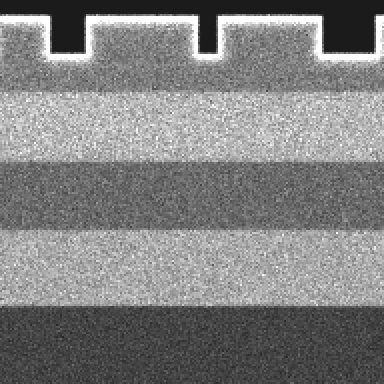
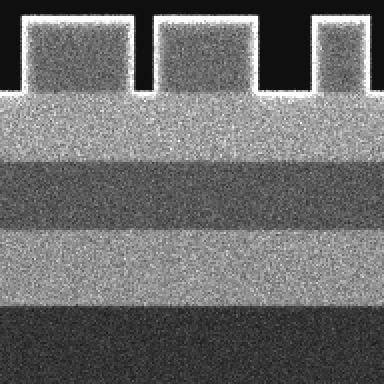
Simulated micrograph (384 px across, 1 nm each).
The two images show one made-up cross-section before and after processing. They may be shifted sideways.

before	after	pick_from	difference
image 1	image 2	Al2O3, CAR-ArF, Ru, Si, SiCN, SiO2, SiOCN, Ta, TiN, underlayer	underlayer removed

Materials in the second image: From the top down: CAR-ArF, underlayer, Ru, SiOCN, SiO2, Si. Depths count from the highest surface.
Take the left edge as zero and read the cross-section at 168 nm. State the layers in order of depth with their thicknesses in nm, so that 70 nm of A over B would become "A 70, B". CAR-ArF 38, underlayer 38, Ru 70, SiOCN 68, SiO2 76, Si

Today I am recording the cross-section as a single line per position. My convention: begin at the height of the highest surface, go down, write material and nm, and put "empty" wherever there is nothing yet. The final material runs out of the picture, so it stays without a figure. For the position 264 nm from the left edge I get empty 76, Ru 70, SiOCN 68, SiO2 76, Si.